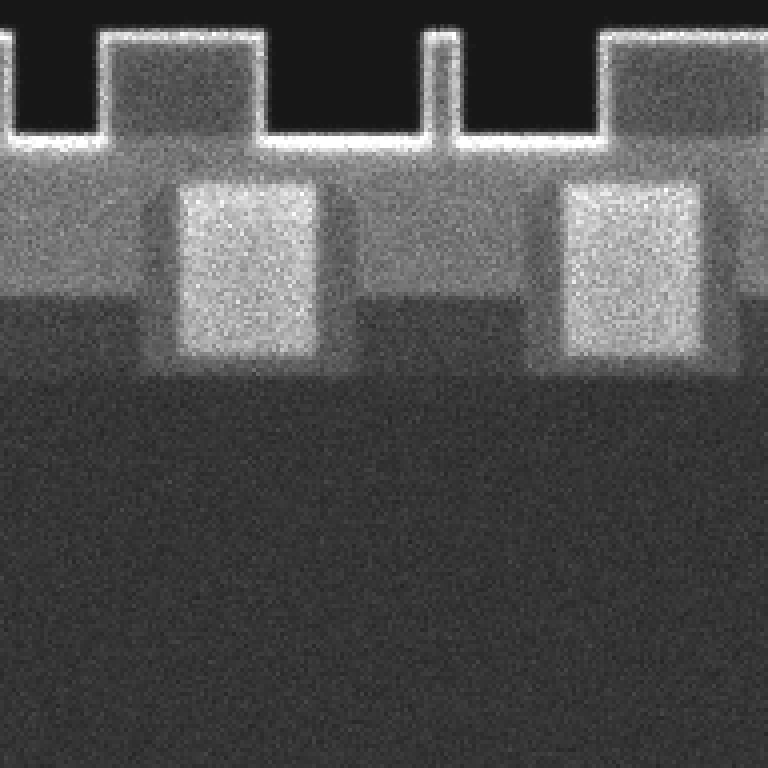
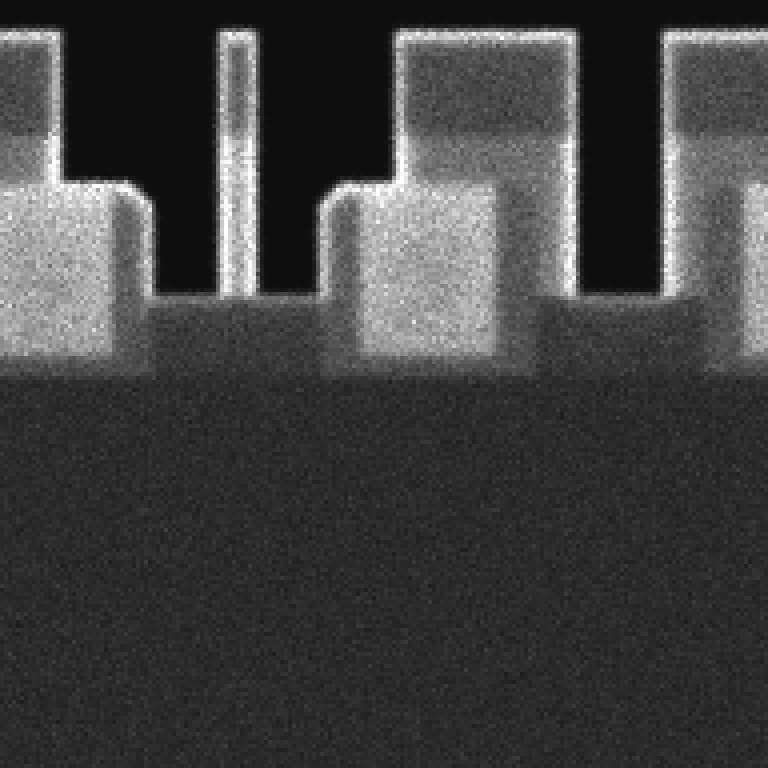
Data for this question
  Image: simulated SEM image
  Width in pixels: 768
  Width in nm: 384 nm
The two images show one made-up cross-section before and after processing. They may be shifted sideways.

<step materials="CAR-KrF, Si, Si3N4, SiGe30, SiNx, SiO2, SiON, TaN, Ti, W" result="removed SiO2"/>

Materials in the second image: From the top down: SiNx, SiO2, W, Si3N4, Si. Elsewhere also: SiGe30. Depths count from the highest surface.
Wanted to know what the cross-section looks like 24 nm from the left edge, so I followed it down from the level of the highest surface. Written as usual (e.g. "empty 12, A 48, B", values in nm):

SiNx 52, SiO2 24, W 86, Si3N4 10, Si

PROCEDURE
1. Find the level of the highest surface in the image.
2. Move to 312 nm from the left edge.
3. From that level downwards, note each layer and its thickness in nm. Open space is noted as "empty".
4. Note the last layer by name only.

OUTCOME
empty 132, SiGe30 40, Si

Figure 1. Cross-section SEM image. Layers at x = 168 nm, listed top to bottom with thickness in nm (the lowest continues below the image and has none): empty 78, Si3N4 94, Si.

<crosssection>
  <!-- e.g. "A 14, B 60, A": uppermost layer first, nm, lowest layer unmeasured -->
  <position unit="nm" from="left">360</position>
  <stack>SiNx 52, SiO2 26, Si3N4 94, Si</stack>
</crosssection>